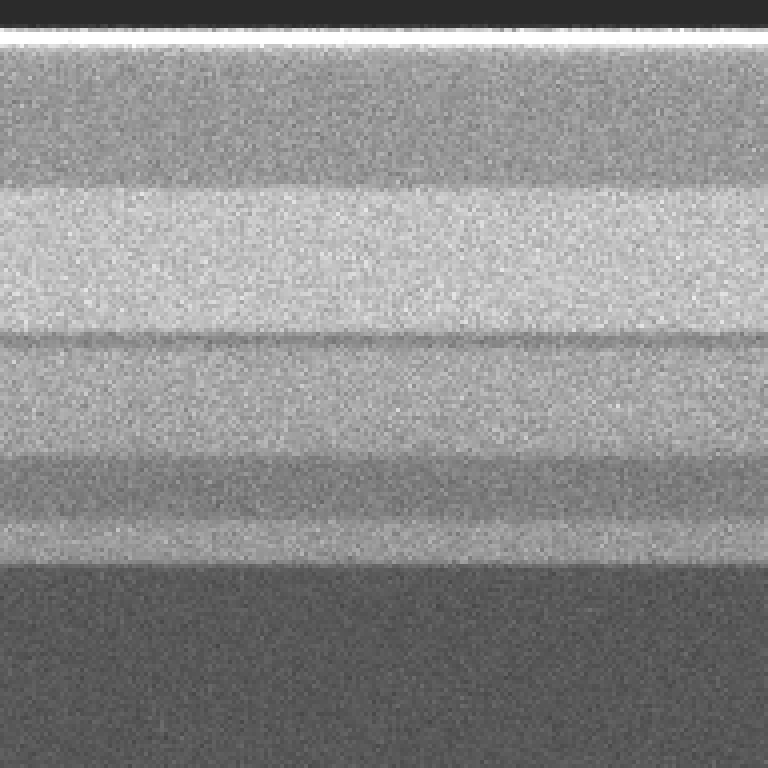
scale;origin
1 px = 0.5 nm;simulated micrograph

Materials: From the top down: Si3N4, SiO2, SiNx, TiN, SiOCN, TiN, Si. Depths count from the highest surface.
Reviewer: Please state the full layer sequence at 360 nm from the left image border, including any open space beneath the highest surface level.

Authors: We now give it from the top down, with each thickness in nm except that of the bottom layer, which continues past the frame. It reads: Si3N4 78, SiO2 72, SiNx 8, TiN 54, SiOCN 32, TiN 22, Si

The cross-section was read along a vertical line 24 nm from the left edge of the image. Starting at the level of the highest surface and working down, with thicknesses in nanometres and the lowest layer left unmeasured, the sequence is Si3N4 78, SiO2 72, SiNx 8, TiN 54, SiOCN 32, TiN 22, Si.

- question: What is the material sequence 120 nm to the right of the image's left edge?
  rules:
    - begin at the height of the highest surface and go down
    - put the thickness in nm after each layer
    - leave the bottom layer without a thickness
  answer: Si3N4 78, SiO2 72, SiNx 8, TiN 54, SiOCN 32, TiN 22, Si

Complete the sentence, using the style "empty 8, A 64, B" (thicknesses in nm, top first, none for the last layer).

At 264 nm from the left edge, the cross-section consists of Si3N4 78, SiO2 72, SiNx 8, TiN 54, SiOCN 32, TiN 22, Si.